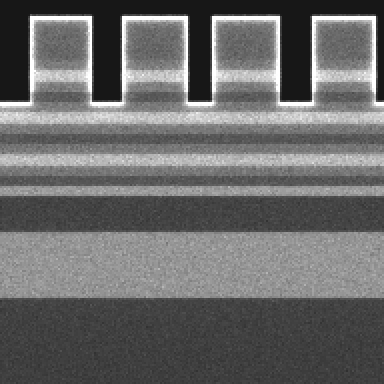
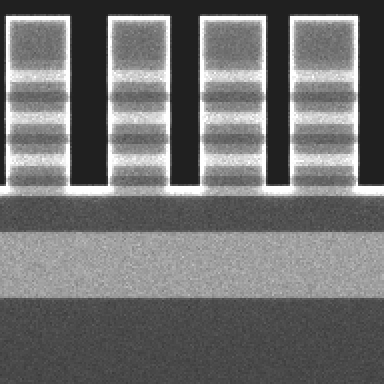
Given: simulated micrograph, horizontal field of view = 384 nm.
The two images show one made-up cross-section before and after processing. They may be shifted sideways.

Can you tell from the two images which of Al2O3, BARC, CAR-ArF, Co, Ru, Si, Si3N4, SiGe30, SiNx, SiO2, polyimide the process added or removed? Yes, it removed Co and Si3N4 and SiGe30.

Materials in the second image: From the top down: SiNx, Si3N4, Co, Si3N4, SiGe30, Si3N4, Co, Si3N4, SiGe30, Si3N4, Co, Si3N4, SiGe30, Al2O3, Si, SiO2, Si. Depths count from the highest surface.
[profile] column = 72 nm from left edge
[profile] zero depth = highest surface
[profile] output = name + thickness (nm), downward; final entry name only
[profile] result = empty 170, Al2O3 10, Si 36, SiO2 66, Si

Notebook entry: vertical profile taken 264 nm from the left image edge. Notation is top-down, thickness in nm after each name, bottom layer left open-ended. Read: SiNx 44, Si3N4 10, Co 12, Si3N4 10, SiGe30 10, Si3N4 10, Co 12, Si3N4 10, SiGe30 10, Si3N4 10, Co 12, Si3N4 10, SiGe30 10, Al2O3 10, Si 36, SiO2 66, Si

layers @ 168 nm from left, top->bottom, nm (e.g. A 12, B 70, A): SiNx 44, Si3N4 10, Co 12, Si3N4 10, SiGe30 10, Si3N4 10, Co 12, Si3N4 10, SiGe30 10, Si3N4 10, Co 12, Si3N4 10, SiGe30 10, Al2O3 10, Si 36, SiO2 66, Si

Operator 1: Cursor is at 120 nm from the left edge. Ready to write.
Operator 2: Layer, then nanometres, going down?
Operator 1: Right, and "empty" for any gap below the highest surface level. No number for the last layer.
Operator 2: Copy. SiNx 44, Si3N4 10, Co 12, Si3N4 10, SiGe30 10, Si3N4 10, Co 12, Si3N4 10, SiGe30 10, Si3N4 10, Co 12, Si3N4 10, SiGe30 10, Al2O3 10, Si 36, SiO2 66, Si